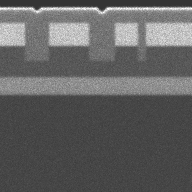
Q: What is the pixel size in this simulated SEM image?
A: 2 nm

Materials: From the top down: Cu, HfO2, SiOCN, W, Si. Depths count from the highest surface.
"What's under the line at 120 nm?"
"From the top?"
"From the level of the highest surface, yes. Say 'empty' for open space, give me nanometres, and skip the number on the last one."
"Cu 30, HfO2 46, SiOCN 62, W 36, Si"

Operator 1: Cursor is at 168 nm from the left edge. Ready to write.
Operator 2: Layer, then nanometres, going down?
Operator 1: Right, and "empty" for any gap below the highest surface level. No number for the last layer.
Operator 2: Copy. Cu 30, HfO2 46, SiOCN 62, W 36, Si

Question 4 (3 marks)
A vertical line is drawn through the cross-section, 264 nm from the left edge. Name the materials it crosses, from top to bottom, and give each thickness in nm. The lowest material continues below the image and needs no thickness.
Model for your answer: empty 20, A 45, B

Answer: Cu 30, HfO2 46, SiOCN 62, W 36, Si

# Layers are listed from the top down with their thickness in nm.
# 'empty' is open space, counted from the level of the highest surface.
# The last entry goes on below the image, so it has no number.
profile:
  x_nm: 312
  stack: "Cu 30, HfO2 46, SiOCN 62, W 36, Si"